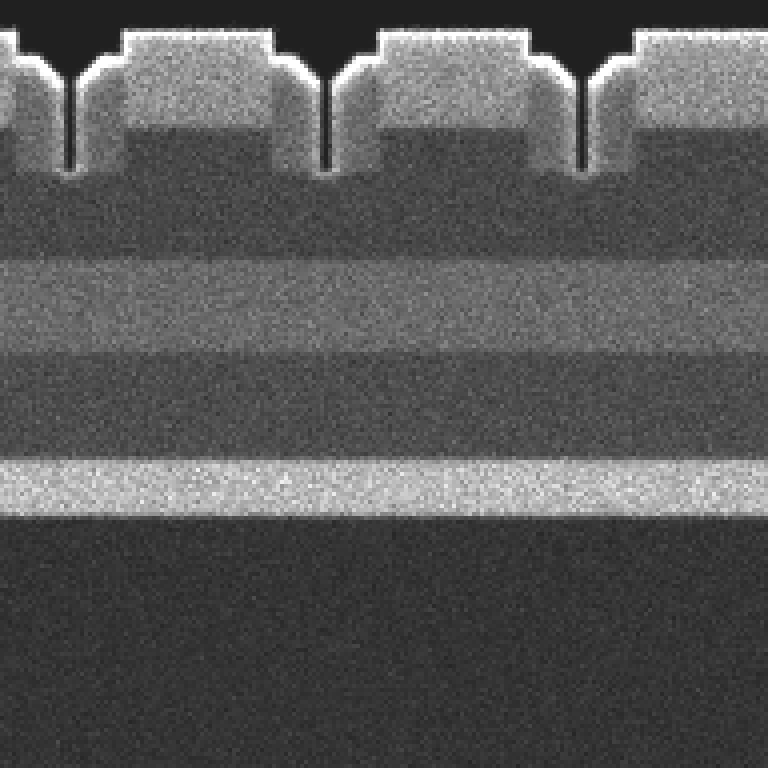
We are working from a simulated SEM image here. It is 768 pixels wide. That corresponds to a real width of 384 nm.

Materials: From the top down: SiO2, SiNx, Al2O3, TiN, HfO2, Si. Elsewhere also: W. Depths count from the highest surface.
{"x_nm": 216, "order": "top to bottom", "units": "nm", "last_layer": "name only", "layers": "W 48, SiNx 66, Al2O3 46, TiN 54, HfO2 28, Si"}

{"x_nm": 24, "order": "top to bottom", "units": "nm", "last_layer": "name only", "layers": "empty 18, SiO2 52, SiNx 44, Al2O3 46, TiN 54, HfO2 28, Si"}